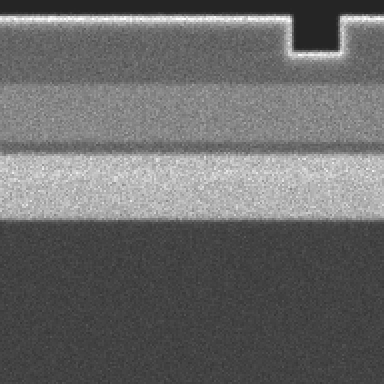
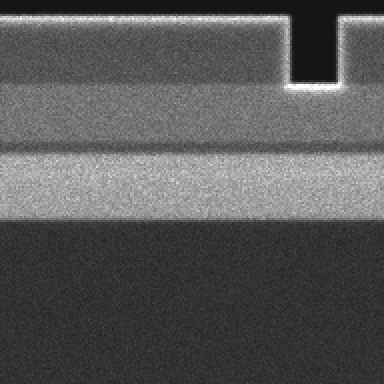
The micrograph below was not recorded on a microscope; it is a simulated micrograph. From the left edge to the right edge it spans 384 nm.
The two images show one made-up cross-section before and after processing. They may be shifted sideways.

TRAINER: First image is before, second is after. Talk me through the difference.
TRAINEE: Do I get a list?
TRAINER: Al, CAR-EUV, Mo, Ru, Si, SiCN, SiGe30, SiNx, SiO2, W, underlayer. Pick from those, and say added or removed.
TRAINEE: removed: underlayer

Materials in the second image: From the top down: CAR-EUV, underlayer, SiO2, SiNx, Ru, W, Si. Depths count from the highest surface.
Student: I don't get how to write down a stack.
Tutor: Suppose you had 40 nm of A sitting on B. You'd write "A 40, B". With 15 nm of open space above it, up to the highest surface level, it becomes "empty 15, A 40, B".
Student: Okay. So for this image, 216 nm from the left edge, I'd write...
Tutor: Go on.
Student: CAR-EUV 36, underlayer 32, SiO2 58, SiNx 12, Ru 16, W 50, Si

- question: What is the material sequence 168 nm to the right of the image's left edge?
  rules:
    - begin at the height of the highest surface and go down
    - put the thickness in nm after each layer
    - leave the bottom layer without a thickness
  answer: CAR-EUV 36, underlayer 32, SiO2 58, SiNx 12, Ru 16, W 50, Si